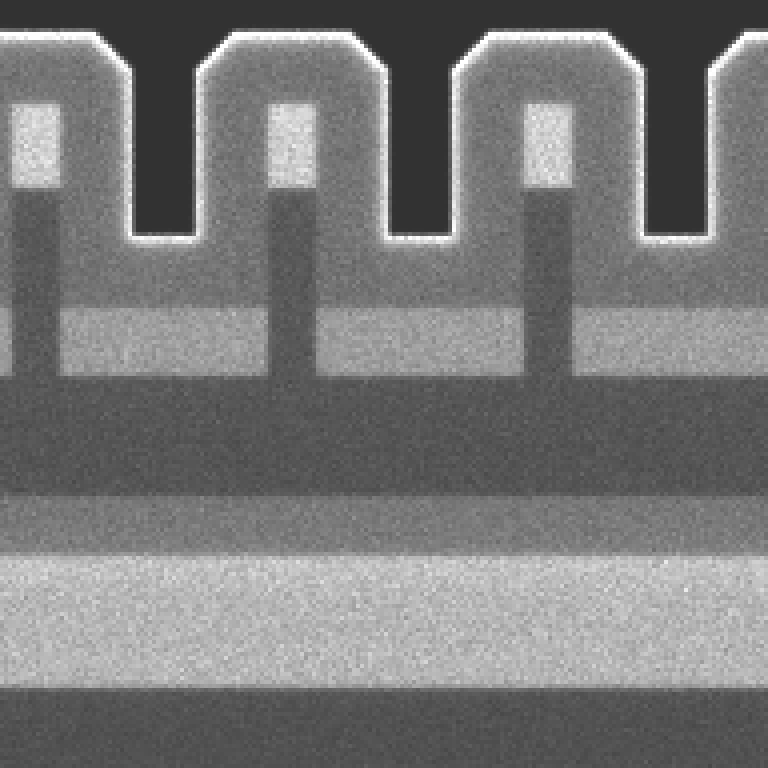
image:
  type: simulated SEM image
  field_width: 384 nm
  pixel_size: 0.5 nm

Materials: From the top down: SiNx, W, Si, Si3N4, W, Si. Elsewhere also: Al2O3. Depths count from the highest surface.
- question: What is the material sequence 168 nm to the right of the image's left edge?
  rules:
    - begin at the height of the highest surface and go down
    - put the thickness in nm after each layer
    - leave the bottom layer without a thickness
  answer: SiNx 138, Al2O3 34, Si 60, Si3N4 30, W 66, Si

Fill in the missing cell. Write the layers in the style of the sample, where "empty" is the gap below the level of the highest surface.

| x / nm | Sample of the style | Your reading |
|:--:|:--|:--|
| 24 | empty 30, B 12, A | SiNx 36, W 42, Si 154, Si3N4 30, W 66, Si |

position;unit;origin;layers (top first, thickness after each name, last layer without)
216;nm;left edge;empty 102, SiNx 36, Al2O3 34, Si 60, Si3N4 30, W 66, Si